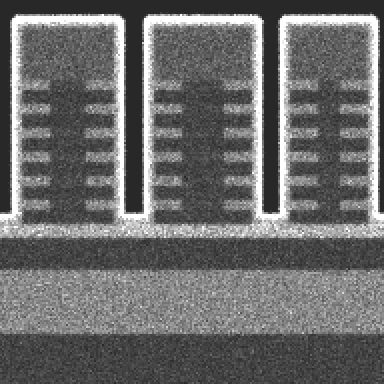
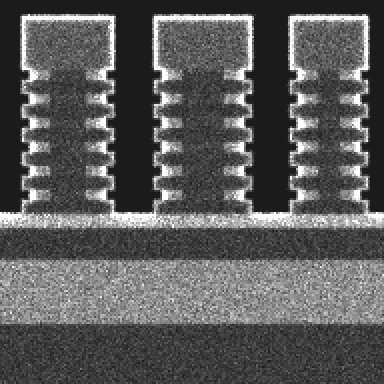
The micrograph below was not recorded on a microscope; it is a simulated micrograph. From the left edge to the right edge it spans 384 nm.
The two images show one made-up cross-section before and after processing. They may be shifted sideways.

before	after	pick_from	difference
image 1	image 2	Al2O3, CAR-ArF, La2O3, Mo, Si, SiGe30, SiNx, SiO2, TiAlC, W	Al2O3 removed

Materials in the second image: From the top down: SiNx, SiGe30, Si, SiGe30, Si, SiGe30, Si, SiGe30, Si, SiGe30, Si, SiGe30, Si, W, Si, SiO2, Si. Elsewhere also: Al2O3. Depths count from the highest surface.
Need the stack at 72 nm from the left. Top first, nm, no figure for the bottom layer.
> SiNx 54, SiGe30 10, Si 14, SiGe30 10, Si 14, SiGe30 10, Si 14, SiGe30 10, Si 14, SiGe30 10, Si 14, SiGe30 10, Si 14, W 14, Si 32, SiO2 64, Si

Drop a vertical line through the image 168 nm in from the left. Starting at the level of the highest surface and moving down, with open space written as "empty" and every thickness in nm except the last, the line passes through SiNx 54, Al2O3 10, Si 14, Al2O3 10, Si 14, Al2O3 10, Si 14, Al2O3 10, Si 14, Al2O3 10, Si 14, Al2O3 10, Si 14, W 14, Si 32, SiO2 64, Si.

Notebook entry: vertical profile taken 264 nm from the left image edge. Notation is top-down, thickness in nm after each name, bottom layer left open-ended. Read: empty 198, W 14, Si 32, SiO2 64, Si